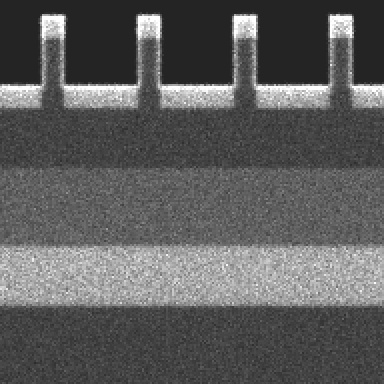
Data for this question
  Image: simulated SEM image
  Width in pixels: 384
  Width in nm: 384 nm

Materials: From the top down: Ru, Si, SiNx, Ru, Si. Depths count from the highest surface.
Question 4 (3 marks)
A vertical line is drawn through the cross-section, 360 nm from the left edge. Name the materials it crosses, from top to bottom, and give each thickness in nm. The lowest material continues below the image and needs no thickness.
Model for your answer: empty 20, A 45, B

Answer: empty 70, Ru 22, Si 60, SiNx 78, Ru 60, Si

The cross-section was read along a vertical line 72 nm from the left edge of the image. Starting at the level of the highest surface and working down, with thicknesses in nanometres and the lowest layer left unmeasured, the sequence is empty 70, Ru 22, Si 60, SiNx 78, Ru 60, Si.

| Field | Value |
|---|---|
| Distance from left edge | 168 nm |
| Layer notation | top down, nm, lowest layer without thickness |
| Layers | empty 70, Ru 22, Si 60, SiNx 78, Ru 60, Si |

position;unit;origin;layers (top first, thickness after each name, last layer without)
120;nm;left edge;empty 70, Ru 22, Si 60, SiNx 78, Ru 60, Si